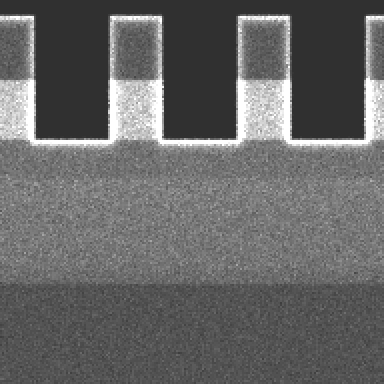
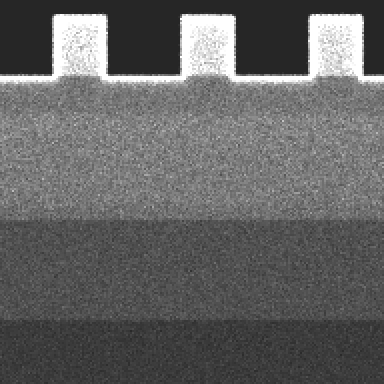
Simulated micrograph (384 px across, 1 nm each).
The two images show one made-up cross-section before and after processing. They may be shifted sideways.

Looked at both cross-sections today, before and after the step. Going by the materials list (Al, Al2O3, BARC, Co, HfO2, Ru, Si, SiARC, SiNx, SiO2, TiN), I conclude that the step removed SiARC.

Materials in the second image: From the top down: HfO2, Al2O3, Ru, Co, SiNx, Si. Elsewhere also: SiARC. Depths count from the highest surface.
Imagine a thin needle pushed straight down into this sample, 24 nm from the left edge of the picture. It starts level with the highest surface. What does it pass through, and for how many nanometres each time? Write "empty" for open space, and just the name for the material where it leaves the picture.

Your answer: empty 60, Al2O3 38, Ru 92, Co 14, SiNx 100, Si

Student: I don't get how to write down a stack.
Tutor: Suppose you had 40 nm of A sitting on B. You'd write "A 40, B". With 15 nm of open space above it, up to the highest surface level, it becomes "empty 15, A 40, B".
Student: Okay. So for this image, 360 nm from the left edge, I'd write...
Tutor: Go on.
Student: HfO2 60, Al2O3 38, Ru 92, Co 14, SiNx 100, Si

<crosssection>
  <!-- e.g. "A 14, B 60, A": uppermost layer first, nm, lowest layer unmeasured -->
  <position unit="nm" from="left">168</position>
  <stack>empty 60, Al2O3 38, Ru 92, Co 14, SiNx 100, Si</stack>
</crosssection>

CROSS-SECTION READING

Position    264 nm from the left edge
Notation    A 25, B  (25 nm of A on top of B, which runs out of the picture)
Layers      empty 60, Al2O3 38, Ru 92, Co 14, SiNx 100, Si